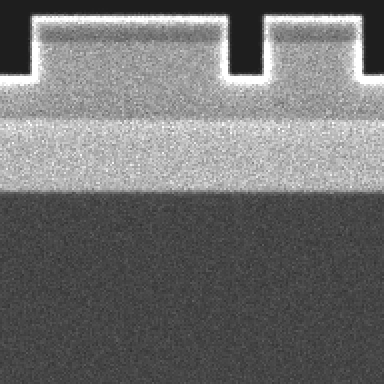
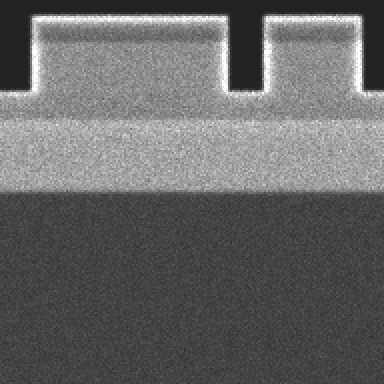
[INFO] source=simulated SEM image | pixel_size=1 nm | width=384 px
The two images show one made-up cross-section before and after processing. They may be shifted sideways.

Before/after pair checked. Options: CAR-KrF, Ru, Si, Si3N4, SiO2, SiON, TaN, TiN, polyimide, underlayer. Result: removed SiO2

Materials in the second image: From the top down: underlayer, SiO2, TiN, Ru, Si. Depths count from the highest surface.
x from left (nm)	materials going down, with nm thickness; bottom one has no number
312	underlayer 26, SiO2 50, TiN 28, Ru 72, Si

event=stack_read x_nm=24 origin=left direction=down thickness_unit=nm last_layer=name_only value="empty 76, TiN 28, Ru 72, Si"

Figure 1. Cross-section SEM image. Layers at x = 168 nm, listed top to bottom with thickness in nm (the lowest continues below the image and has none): underlayer 26, SiO2 50, TiN 28, Ru 72, Si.